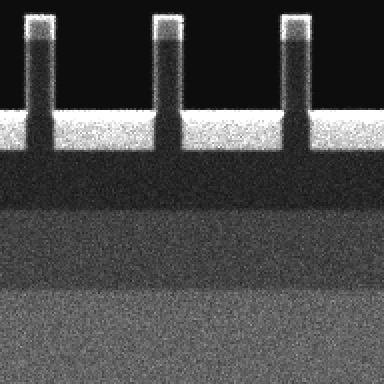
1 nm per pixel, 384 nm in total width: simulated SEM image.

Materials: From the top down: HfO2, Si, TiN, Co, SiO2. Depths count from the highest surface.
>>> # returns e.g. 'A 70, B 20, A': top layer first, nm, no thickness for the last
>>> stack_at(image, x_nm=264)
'empty 96, HfO2 38, Si 60, TiN 80, Co 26, SiO2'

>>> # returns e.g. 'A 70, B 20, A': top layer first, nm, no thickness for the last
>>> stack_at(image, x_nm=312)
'empty 96, HfO2 38, Si 60, TiN 80, Co 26, SiO2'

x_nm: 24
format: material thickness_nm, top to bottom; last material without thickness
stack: empty 96, HfO2 38, Si 60, TiN 80, Co 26, SiO2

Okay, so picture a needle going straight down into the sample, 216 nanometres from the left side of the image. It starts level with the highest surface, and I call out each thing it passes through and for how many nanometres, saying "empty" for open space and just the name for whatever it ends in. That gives empty 96, HfO2 38, Si 60, TiN 80, Co 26, SiO2